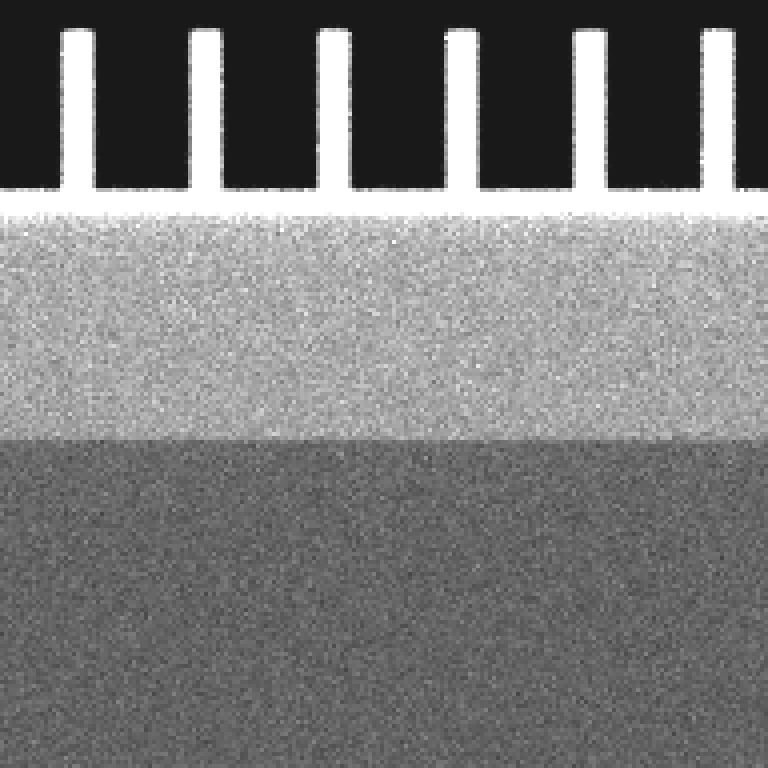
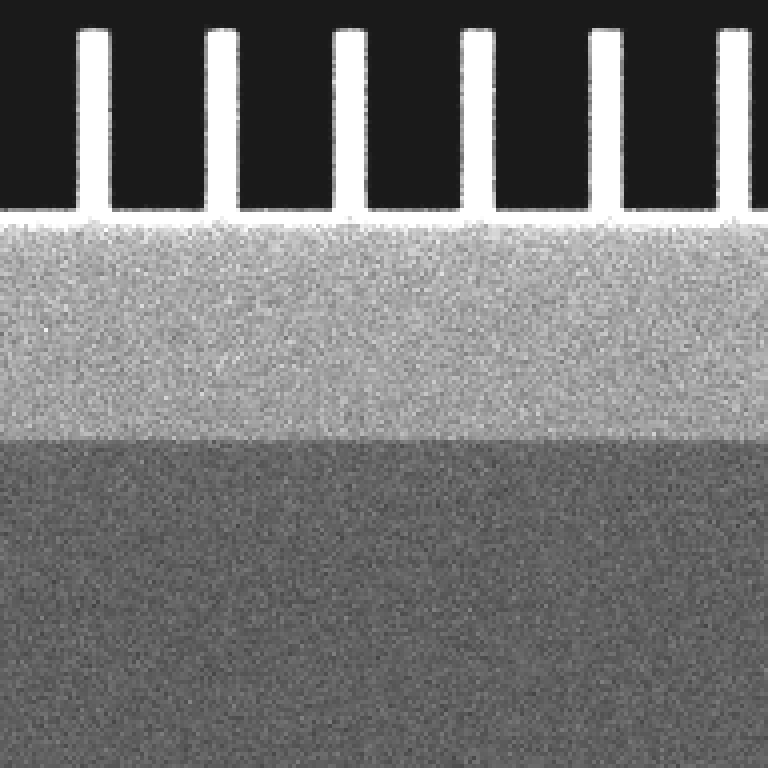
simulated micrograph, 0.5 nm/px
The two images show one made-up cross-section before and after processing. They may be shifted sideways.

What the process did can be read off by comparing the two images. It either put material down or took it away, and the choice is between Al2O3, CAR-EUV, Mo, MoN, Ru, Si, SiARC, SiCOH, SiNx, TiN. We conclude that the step removed Ru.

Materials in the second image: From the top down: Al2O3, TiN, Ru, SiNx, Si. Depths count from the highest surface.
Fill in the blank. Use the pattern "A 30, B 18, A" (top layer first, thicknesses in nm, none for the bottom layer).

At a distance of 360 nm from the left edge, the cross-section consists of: Al2O3 26, TiN 54, Ru 10, SiNx 114, Si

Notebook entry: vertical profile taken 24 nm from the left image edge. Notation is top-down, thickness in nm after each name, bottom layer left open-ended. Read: empty 90, SiNx 114, Si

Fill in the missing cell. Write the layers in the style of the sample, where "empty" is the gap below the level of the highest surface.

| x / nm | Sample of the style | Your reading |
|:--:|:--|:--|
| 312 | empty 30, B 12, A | empty 90, SiNx 114, Si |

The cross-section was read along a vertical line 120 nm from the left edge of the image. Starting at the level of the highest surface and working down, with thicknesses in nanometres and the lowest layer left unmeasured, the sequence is empty 90, SiNx 114, Si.